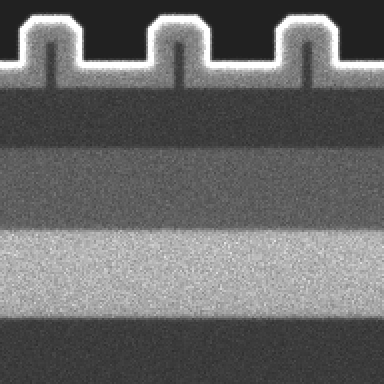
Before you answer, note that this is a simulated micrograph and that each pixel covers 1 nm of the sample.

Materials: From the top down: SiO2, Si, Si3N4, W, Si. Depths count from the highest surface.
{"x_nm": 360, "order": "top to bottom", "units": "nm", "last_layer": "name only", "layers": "empty 46, SiO2 26, Si 60, Si3N4 82, W 88, Si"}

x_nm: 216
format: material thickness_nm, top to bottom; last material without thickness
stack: empty 46, SiO2 26, Si 60, Si3N4 82, W 88, Si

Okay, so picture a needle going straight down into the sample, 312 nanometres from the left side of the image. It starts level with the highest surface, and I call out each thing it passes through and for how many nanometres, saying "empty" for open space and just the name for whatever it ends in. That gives SiO2 72, Si 60, Si3N4 82, W 88, Si